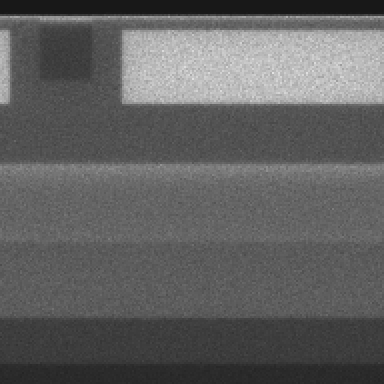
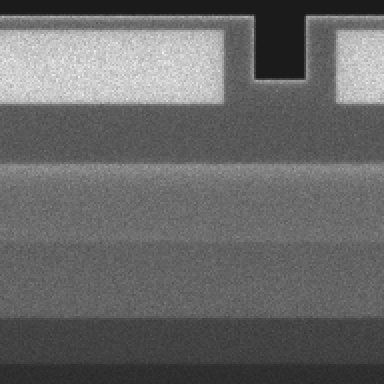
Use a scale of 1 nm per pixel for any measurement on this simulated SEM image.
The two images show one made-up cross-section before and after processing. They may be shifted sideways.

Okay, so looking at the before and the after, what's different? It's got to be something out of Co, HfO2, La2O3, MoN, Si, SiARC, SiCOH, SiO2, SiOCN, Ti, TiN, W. SiARC, removed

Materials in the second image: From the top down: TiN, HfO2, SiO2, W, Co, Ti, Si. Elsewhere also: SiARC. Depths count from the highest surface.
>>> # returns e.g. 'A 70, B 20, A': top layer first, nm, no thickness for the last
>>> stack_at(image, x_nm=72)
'TiN 14, HfO2 74, SiO2 60, W 78, Co 76, Ti 46, Si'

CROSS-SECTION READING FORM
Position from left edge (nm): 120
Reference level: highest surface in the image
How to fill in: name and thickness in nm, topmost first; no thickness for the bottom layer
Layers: TiN 14, HfO2 74, SiO2 60, W 78, Co 76, Ti 46, Si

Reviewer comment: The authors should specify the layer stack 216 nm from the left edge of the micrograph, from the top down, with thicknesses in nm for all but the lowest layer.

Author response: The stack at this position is TiN 14, HfO2 74, SiO2 60, W 78, Co 76, Ti 46, Si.